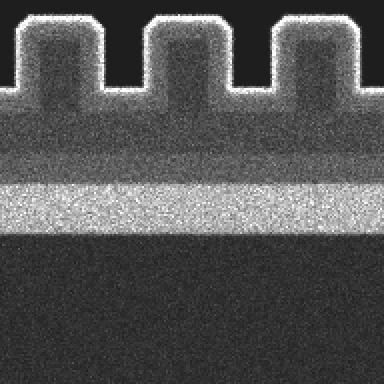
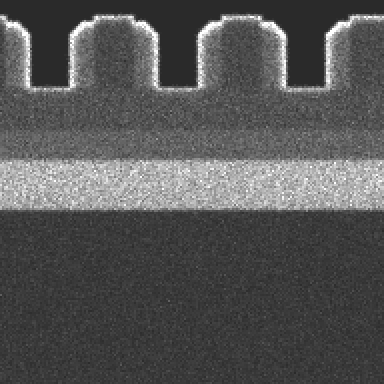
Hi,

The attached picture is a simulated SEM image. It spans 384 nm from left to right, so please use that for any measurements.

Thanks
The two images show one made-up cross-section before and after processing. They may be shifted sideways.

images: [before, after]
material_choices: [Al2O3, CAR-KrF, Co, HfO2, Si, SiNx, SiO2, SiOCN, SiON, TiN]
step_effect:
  removed: Al2O3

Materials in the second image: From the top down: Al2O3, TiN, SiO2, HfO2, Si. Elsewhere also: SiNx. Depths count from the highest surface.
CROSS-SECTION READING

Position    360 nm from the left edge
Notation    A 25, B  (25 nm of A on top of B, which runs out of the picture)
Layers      SiNx 72, TiN 42, SiO2 30, HfO2 50, Si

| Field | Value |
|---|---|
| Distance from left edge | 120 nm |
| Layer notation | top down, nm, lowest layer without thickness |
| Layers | SiNx 72, TiN 42, SiO2 30, HfO2 50, Si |